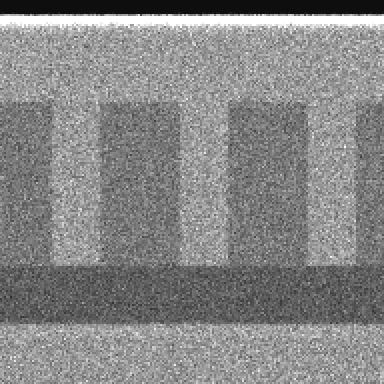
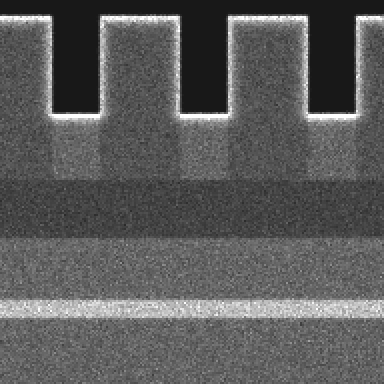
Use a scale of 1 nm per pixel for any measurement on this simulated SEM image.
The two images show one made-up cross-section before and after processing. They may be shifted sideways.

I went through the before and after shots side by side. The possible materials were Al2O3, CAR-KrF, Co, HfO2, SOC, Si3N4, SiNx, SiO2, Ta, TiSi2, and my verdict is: removed, SiO2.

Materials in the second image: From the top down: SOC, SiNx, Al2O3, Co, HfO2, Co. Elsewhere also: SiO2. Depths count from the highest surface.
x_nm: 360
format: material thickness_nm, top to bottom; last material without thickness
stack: SOC 164, SiNx 58, Al2O3 14, Co 48, HfO2 18, Co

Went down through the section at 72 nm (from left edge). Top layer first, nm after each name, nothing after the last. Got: empty 98, SiO2 66, SiNx 58, Al2O3 14, Co 48, HfO2 18, Co